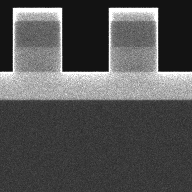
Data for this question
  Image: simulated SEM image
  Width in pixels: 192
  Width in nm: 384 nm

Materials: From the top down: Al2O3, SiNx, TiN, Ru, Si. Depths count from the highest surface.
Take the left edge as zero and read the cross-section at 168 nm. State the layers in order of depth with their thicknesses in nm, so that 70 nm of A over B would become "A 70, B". empty 128, Ru 56, Si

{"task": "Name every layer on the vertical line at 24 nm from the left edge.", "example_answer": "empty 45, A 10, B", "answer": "empty 128, Ru 56, Si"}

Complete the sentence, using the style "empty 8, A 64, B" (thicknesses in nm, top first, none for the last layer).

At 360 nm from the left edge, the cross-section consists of empty 128, Ru 56, Si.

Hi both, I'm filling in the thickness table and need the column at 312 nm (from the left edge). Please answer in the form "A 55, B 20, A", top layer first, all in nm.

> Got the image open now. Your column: Al2O3 26, SiNx 52, TiN 50, Ru 56, Si